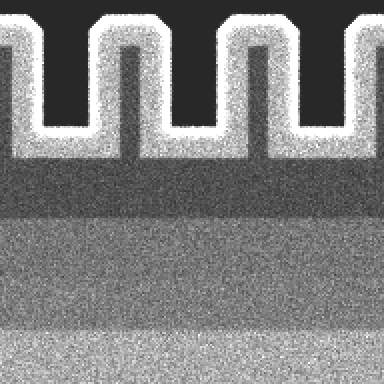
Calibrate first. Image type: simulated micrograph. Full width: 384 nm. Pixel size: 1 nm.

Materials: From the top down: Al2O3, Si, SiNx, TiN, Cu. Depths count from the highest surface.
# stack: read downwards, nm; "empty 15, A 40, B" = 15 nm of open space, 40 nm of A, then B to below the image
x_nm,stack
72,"empty 112, Al2O3 30, Si 60, SiNx 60, TiN 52, Cu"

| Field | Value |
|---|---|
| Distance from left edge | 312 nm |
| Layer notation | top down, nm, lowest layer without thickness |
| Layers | empty 112, Al2O3 30, Si 60, SiNx 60, TiN 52, Cu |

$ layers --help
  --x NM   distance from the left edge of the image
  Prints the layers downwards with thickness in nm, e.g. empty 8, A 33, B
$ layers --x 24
Al2O3 142, Si 60, SiNx 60, TiN 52, Cu